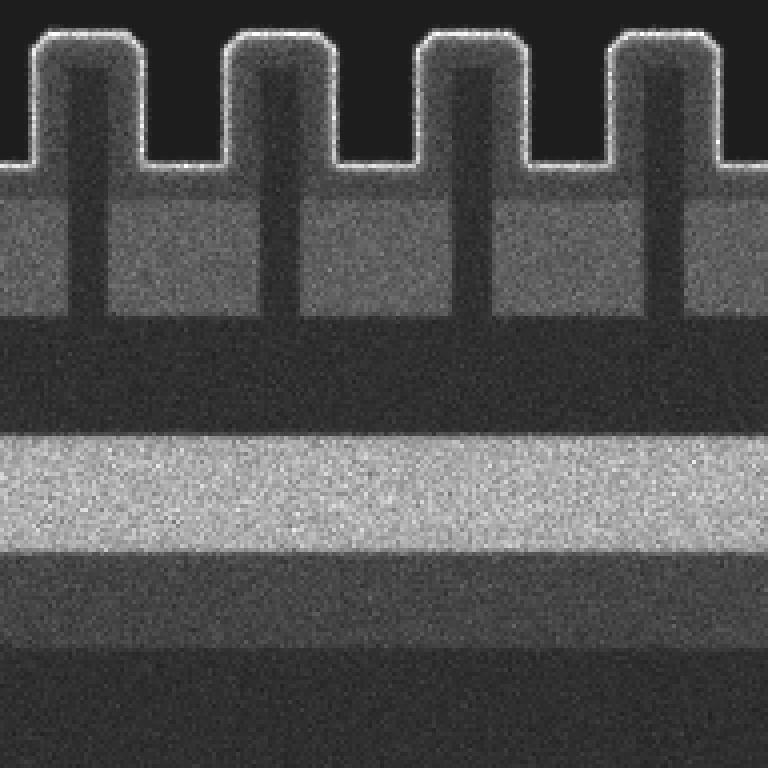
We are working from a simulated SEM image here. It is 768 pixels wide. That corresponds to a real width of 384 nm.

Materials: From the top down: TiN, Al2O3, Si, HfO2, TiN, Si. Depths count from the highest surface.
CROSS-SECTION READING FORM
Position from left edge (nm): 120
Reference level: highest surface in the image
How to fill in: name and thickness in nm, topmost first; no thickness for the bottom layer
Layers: TiN 84, Al2O3 58, Si 60, HfO2 58, TiN 48, Si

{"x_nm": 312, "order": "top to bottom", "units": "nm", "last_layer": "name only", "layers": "TiN 84, Al2O3 58, Si 60, HfO2 58, TiN 48, Si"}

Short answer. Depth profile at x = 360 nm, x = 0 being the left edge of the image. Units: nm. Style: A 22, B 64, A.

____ empty 66, TiN 18, Al2O3 58, Si 60, HfO2 58, TiN 48, Si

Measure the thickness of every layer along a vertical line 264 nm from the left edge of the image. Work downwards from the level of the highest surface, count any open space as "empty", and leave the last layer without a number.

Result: empty 66, TiN 18, Al2O3 58, Si 60, HfO2 58, TiN 48, Si